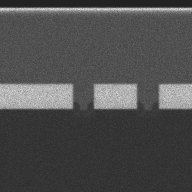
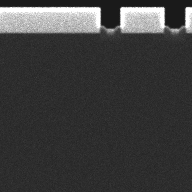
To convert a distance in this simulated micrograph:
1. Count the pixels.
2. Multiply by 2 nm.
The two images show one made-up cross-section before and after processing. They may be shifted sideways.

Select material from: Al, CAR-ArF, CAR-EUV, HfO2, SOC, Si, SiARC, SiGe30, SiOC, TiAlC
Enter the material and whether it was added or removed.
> SOC / removed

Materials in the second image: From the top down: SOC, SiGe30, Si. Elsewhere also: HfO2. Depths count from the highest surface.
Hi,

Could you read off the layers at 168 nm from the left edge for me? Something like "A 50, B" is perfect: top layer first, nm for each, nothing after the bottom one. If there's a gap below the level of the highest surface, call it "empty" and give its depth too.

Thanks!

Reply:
HfO2 50, Si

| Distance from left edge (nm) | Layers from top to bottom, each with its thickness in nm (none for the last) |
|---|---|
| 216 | empty 42, SOC 10, SiGe30 14, Si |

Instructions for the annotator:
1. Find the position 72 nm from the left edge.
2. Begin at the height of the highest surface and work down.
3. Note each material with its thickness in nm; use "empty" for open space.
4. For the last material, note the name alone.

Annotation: HfO2 50, Si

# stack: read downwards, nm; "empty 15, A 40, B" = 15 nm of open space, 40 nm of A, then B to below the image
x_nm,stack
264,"HfO2 50, Si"